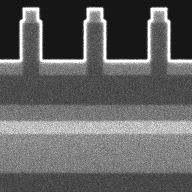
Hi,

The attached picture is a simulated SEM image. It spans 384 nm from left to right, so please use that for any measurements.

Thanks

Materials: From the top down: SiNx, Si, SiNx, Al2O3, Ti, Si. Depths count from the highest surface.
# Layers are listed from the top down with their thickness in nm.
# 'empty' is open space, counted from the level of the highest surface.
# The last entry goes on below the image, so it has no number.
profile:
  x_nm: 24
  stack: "empty 104, SiNx 30, Si 60, SiNx 32, Al2O3 26, Ti 78, Si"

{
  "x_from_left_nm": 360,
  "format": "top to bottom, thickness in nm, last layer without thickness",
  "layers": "empty 104, SiNx 30, Si 60, SiNx 32, Al2O3 26, Ti 78, Si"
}